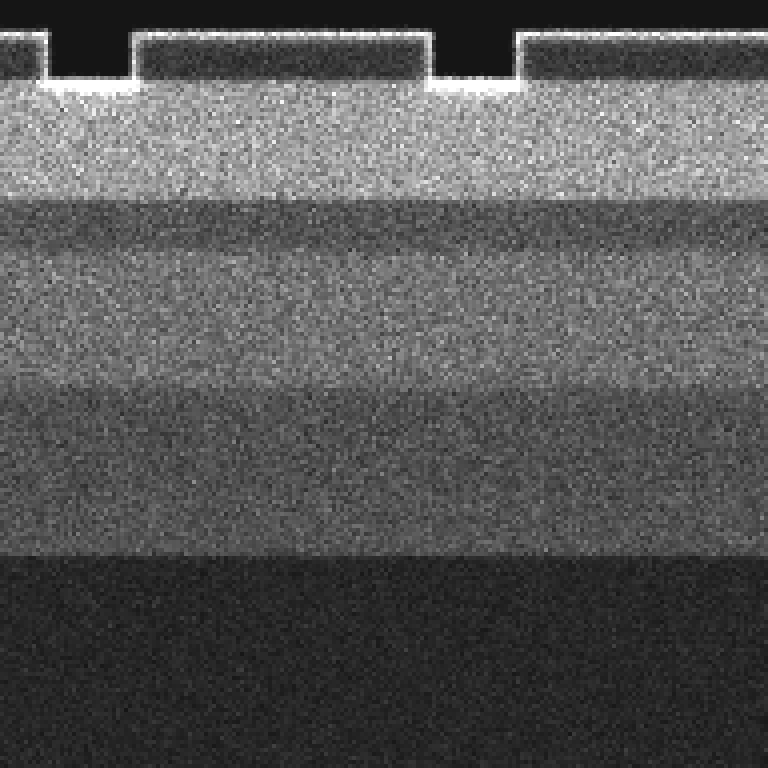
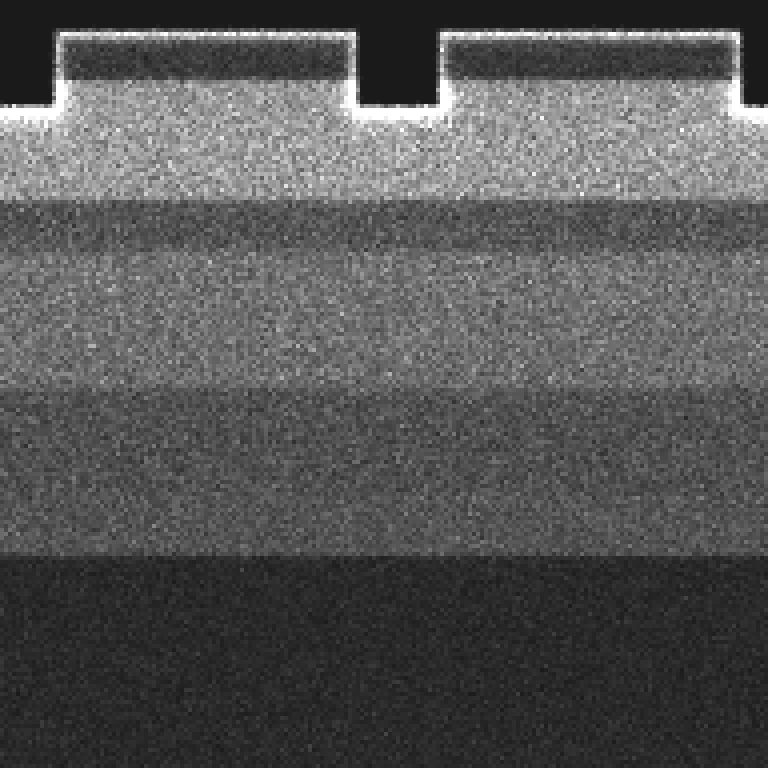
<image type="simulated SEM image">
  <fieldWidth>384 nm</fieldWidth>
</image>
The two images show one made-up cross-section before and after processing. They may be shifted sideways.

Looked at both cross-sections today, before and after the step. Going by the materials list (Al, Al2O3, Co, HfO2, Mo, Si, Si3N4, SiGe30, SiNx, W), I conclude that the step removed HfO2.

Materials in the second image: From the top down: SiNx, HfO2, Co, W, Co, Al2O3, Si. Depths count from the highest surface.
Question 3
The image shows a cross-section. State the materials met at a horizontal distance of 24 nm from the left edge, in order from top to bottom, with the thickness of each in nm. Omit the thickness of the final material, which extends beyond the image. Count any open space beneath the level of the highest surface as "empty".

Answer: empty 38, HfO2 46, Co 26, W 68, Co 52, Al2O3 32, Si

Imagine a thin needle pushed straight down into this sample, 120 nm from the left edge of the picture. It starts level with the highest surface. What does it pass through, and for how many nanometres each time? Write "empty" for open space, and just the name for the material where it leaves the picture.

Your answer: SiNx 24, HfO2 60, Co 26, W 68, Co 52, Al2O3 32, Si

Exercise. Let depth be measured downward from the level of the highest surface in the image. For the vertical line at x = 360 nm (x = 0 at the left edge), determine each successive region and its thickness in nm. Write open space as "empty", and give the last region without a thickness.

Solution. SiNx 24, HfO2 60, Co 26, W 68, Co 52, Al2O3 32, Si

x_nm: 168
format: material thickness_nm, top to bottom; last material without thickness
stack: SiNx 24, HfO2 60, Co 26, W 68, Co 52, Al2O3 32, Si